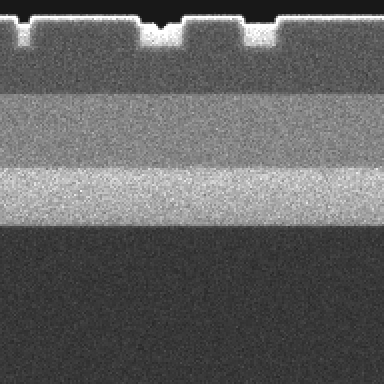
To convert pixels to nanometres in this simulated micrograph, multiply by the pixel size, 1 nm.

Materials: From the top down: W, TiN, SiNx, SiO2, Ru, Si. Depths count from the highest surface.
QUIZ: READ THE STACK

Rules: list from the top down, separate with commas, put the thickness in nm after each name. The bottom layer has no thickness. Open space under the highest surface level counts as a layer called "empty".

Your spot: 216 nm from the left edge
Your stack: TiN 6, SiNx 72, SiO2 74, Ru 58, Si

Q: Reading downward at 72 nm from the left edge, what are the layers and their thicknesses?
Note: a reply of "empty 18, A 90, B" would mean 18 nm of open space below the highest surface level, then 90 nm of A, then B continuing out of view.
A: TiN 6, SiNx 72, SiO2 74, Ru 58, Si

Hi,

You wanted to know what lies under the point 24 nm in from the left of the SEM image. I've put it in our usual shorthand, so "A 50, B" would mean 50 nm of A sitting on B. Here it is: empty 8, W 22, TiN 6, SiNx 42, SiO2 74, Ru 58, Si